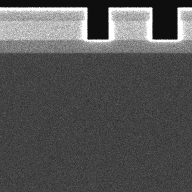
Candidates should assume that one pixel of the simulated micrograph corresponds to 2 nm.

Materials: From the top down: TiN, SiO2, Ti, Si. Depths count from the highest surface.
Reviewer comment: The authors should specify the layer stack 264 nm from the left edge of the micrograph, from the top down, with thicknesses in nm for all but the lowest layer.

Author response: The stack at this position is TiN 26, SiO2 38, Ti 26, Si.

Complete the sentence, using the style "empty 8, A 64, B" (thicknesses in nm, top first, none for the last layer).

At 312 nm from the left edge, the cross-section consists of empty 64, Ti 26, Si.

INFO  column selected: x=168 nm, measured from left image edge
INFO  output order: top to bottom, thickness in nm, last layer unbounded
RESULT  TiN 26, SiO2 38, Ti 26, Si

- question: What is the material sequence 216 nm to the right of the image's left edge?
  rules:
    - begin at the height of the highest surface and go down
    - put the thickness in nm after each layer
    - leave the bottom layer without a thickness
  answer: empty 64, Ti 26, Si